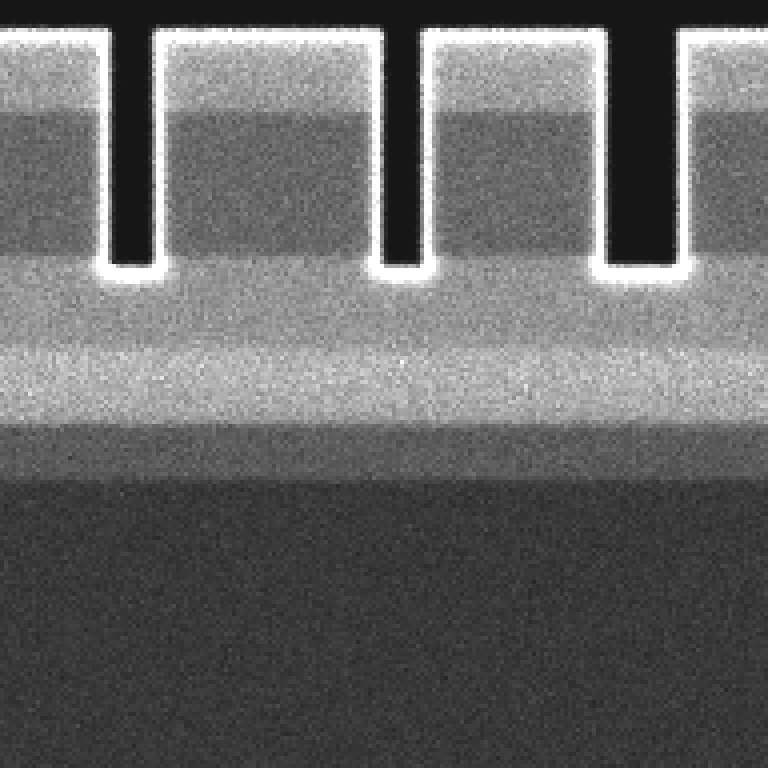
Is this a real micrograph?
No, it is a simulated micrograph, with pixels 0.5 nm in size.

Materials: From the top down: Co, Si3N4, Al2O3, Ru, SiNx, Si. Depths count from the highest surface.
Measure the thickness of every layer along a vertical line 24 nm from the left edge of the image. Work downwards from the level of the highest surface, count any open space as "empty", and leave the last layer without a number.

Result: Co 40, Si3N4 72, Al2O3 46, Ru 38, SiNx 28, Si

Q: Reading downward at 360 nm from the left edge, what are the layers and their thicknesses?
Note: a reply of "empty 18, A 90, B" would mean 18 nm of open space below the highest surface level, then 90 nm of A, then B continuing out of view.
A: Co 40, Si3N4 72, Al2O3 46, Ru 38, SiNx 28, Si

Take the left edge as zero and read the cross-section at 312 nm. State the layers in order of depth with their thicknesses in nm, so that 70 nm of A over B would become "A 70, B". empty 118, Al2O3 40, Ru 38, SiNx 28, Si